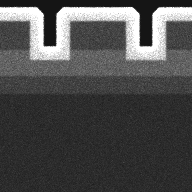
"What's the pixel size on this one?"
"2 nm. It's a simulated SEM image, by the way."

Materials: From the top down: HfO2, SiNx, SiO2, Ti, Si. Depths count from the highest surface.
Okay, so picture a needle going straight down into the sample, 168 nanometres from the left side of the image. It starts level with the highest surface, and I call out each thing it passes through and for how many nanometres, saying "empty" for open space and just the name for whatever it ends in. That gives HfO2 26, SiNx 58, SiO2 52, Ti 36, Si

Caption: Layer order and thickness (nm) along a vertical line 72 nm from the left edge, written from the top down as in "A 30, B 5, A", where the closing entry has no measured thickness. HfO2 104, SiO2 32, Ti 36, Si